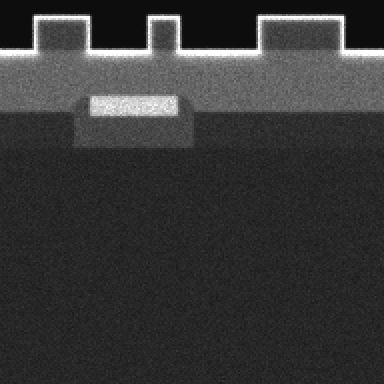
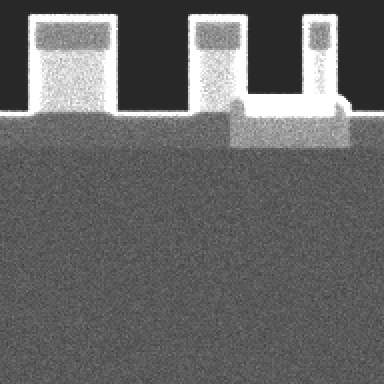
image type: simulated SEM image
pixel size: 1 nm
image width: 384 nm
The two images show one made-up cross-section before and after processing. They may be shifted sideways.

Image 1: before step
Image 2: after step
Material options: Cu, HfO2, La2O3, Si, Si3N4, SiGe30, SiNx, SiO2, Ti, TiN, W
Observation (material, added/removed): SiO2, removed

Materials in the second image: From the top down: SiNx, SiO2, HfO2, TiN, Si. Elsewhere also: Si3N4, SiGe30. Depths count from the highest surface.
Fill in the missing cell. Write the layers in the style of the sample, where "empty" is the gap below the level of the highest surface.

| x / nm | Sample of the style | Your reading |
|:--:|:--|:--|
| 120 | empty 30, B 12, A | empty 96, SiGe30 36, Si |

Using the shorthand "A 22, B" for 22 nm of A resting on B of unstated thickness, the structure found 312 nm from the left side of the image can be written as SiNx 34, SiO2 46, HfO2 20, TiN 32, Si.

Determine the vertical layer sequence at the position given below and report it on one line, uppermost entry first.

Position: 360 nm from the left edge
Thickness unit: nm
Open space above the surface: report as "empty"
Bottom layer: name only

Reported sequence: empty 96, SiGe30 36, Si